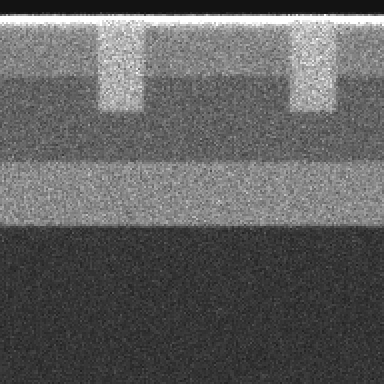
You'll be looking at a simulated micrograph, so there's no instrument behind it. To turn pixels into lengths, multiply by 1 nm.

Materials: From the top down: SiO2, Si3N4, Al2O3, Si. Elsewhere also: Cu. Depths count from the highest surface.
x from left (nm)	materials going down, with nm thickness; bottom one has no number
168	SiO2 60, Si3N4 86, Al2O3 64, Si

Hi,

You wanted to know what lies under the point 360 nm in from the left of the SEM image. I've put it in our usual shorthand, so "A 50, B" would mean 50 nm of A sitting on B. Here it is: SiO2 60, Si3N4 86, Al2O3 64, Si